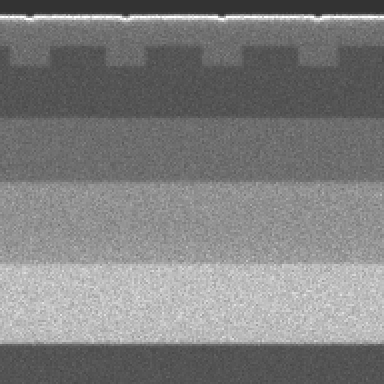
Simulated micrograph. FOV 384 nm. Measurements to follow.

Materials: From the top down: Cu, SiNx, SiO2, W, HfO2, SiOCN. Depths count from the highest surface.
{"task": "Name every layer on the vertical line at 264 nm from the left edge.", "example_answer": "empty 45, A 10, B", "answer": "Cu 30, SiNx 72, SiO2 64, W 82, HfO2 80, SiOCN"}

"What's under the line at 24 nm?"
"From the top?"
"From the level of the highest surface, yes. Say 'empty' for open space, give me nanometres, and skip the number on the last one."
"Cu 50, SiNx 52, SiO2 64, W 82, HfO2 80, SiOCN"